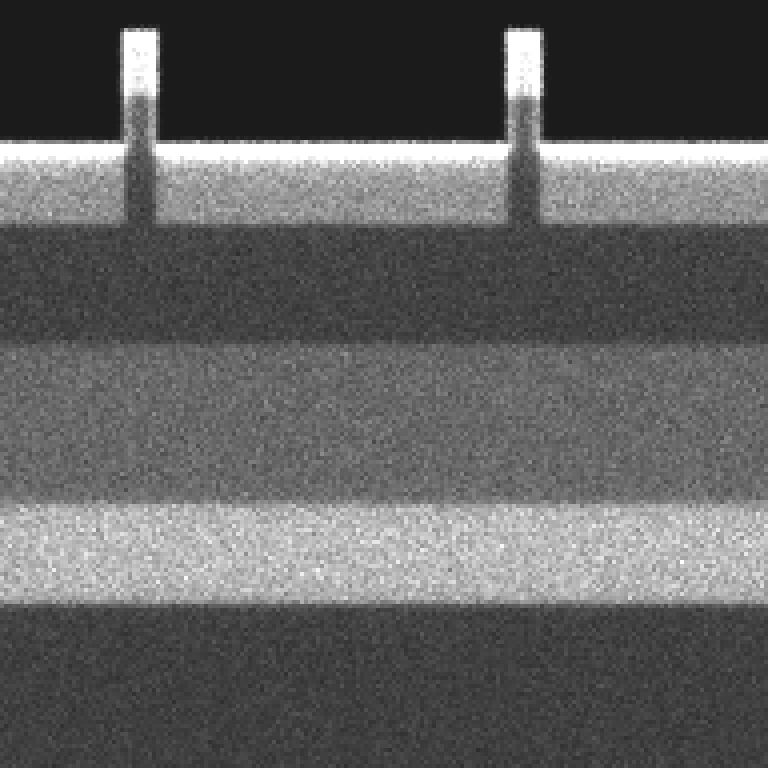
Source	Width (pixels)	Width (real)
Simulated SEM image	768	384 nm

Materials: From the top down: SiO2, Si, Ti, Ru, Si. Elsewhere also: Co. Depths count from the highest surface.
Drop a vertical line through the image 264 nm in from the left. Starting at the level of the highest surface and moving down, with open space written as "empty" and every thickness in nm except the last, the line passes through Co 32, Si 124, Ti 80, Ru 50, Si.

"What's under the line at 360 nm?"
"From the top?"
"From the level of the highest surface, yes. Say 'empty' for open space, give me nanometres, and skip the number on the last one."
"empty 56, SiO2 40, Si 60, Ti 80, Ru 50, Si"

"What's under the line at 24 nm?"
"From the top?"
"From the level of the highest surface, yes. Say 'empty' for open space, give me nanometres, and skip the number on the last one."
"empty 56, SiO2 40, Si 60, Ti 80, Ru 50, Si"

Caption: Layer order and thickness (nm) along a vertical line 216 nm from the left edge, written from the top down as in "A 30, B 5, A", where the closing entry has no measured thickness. empty 56, SiO2 40, Si 60, Ti 80, Ru 50, Si